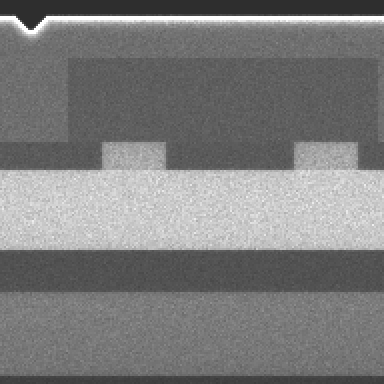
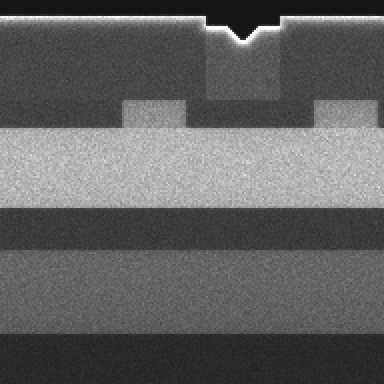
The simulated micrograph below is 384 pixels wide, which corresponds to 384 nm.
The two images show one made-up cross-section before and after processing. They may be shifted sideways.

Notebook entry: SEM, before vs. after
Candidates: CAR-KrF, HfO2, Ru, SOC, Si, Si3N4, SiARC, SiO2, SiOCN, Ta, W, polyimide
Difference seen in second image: SiO2 removed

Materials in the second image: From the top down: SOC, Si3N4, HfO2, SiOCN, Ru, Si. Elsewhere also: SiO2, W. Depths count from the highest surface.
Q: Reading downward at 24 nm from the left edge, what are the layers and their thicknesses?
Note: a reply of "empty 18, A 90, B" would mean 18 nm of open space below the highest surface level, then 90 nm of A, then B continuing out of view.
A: SOC 84, Si3N4 28, HfO2 80, SiOCN 42, Ru 84, Si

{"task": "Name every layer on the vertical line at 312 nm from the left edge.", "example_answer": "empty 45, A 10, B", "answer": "SOC 84, Si3N4 28, HfO2 80, SiOCN 42, Ru 84, Si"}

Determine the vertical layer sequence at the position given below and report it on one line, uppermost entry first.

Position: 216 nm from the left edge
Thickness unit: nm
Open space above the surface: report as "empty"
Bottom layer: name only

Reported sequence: empty 10, SiO2 74, Si3N4 28, HfO2 80, SiOCN 42, Ru 84, Si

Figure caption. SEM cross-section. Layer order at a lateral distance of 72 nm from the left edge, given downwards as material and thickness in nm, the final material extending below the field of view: SOC 84, Si3N4 28, HfO2 80, SiOCN 42, Ru 84, Si